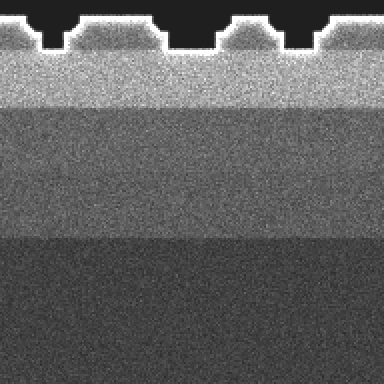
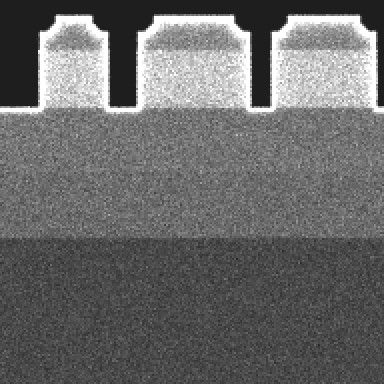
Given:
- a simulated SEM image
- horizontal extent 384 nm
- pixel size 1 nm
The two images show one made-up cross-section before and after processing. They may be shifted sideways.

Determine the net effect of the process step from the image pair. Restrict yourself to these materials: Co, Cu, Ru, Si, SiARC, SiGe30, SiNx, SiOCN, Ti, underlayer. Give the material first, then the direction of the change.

Ru: removed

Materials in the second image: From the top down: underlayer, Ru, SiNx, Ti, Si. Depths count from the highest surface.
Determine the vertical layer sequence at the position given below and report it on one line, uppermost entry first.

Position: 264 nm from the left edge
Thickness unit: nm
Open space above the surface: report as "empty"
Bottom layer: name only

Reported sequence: empty 92, SiNx 64, Ti 66, Si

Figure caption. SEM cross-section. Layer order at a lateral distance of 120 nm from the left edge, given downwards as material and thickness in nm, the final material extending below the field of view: empty 92, SiNx 64, Ti 66, Si